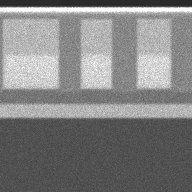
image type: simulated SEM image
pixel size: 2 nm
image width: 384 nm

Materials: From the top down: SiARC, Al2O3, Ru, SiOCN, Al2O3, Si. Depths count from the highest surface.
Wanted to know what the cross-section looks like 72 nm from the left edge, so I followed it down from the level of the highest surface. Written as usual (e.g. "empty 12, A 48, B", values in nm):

SiARC 22, Al2O3 72, Ru 68, SiOCN 30, Al2O3 28, Si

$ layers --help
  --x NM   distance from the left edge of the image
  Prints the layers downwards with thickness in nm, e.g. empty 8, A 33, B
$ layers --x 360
SiARC 168, SiOCN 24, Al2O3 28, Si